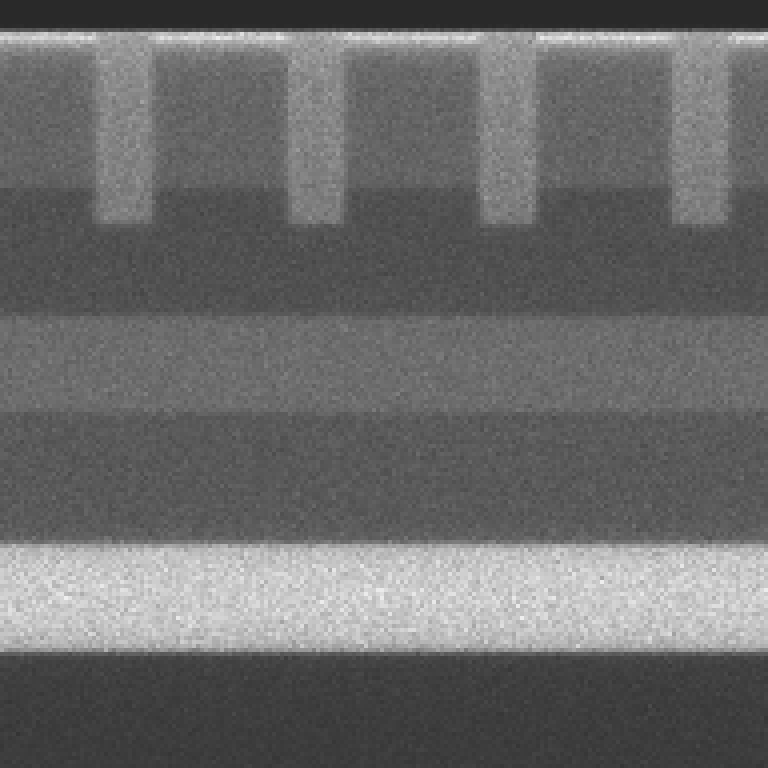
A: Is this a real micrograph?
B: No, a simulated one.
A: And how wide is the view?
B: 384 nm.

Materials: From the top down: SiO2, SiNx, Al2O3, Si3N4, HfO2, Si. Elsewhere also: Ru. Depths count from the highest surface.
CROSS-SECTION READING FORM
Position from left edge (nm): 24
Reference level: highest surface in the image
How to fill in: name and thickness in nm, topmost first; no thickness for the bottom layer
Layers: SiO2 78, SiNx 64, Al2O3 48, Si3N4 66, HfO2 54, Si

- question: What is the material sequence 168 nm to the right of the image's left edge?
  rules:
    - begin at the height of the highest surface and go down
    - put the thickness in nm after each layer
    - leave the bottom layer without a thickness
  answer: Ru 96, SiNx 46, Al2O3 48, Si3N4 66, HfO2 54, Si